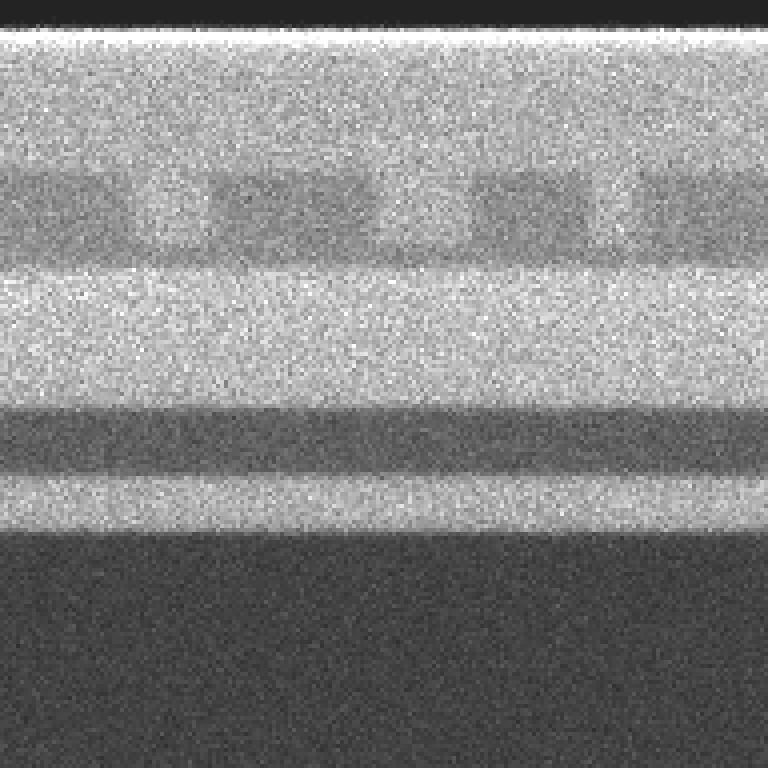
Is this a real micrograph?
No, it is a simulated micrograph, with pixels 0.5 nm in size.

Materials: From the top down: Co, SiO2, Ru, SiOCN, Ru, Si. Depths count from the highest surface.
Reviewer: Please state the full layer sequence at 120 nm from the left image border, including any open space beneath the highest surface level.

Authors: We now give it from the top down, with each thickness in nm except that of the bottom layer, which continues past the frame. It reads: Co 70, SiO2 48, Ru 70, SiOCN 34, Ru 28, Si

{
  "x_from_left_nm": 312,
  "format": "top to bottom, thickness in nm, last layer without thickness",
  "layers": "Co 106, SiO2 12, Ru 70, SiOCN 34, Ru 28, Si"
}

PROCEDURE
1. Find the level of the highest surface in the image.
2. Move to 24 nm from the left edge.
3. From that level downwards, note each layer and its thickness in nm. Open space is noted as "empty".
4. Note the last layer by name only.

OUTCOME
Co 70, SiO2 48, Ru 70, SiOCN 34, Ru 28, Si